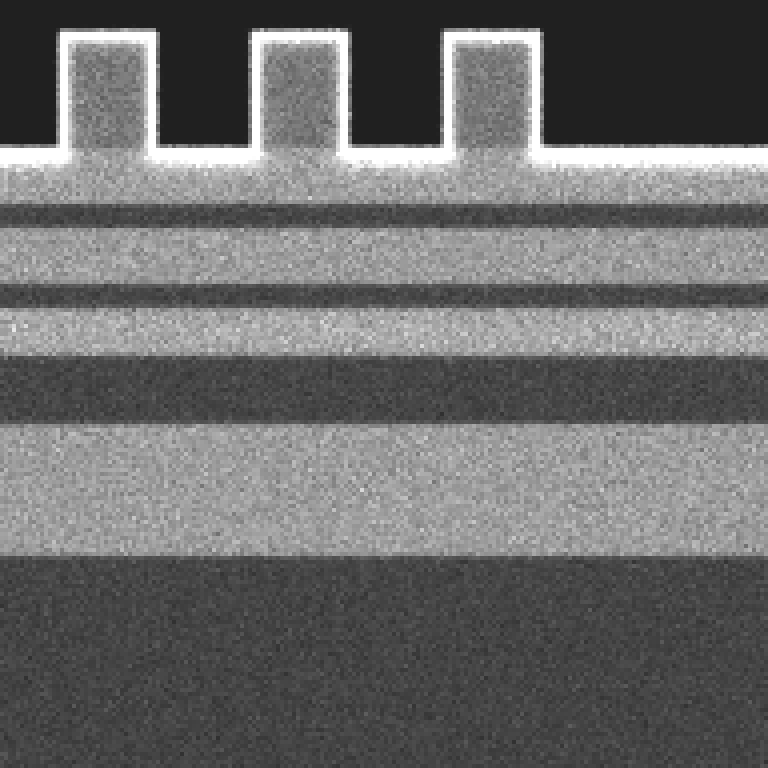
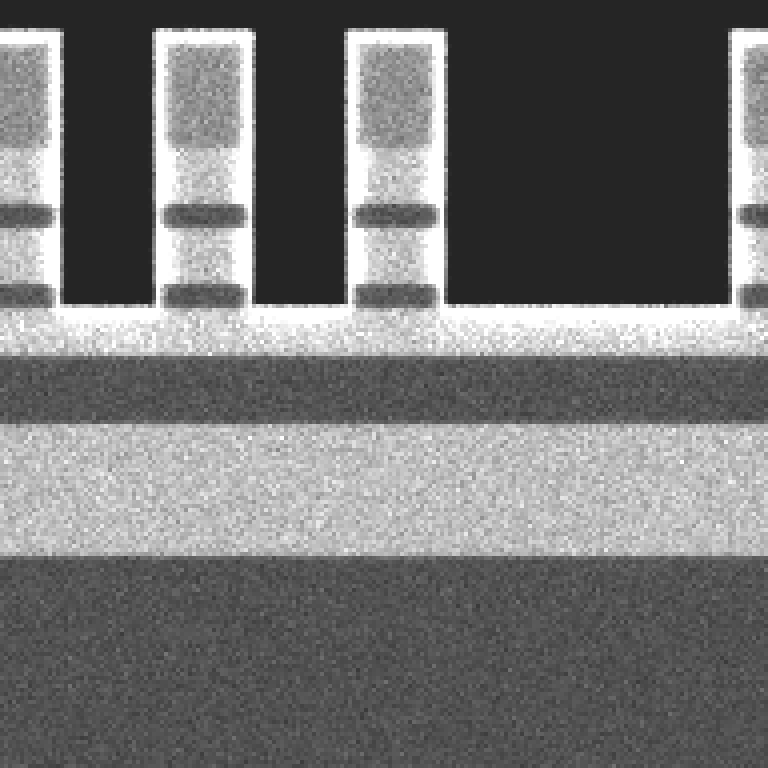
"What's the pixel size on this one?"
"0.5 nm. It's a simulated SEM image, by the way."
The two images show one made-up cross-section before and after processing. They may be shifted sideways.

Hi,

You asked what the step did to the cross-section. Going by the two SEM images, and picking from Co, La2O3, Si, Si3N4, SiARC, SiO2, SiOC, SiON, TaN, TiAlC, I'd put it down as Si and SiO2, removed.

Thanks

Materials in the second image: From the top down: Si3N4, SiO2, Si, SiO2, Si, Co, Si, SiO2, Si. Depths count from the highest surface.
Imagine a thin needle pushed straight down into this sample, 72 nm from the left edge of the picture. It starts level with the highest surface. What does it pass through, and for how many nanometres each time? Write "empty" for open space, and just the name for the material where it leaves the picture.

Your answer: empty 138, Co 24, Si 34, SiO2 66, Si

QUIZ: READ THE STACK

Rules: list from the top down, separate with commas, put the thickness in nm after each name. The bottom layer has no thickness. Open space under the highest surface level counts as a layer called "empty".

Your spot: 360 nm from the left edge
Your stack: empty 138, Co 24, Si 34, SiO2 66, Si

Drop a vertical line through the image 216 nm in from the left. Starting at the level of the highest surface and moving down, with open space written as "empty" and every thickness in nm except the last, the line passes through Si3N4 58, SiO2 28, Si 12, SiO2 28, Si 12, Co 24, Si 34, SiO2 66, Si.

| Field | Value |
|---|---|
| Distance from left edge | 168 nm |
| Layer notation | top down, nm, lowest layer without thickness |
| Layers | empty 138, Co 24, Si 34, SiO2 66, Si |